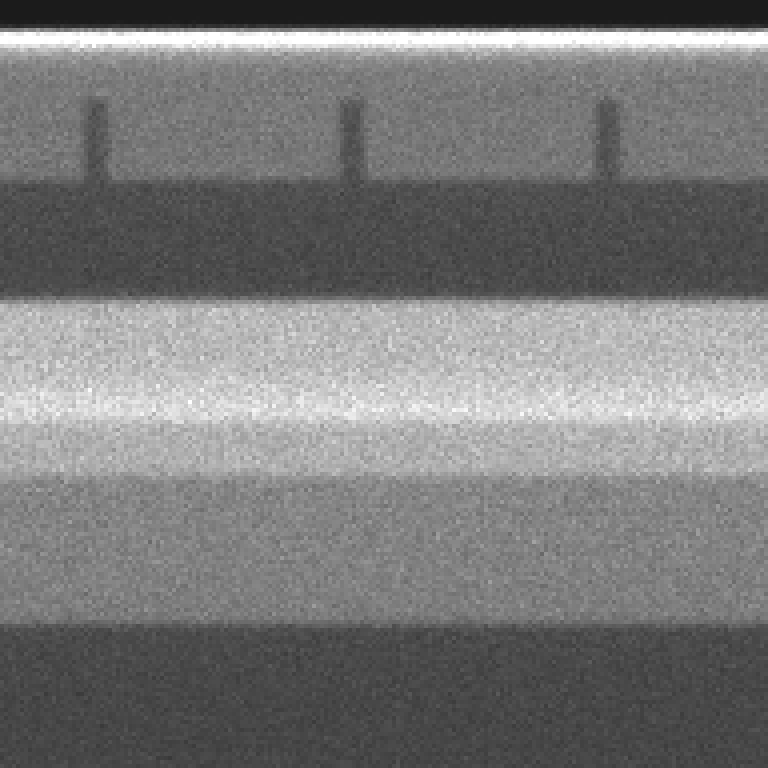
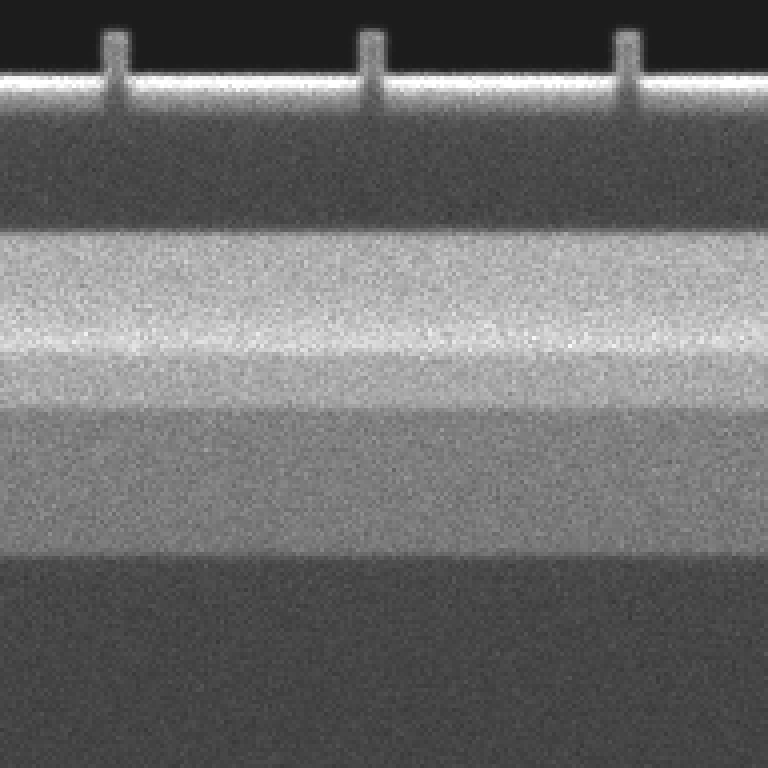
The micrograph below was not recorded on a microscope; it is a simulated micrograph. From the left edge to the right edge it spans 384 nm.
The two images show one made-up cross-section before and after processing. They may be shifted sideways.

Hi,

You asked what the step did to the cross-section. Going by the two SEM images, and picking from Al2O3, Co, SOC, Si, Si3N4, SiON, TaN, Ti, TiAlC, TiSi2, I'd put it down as SOC, removed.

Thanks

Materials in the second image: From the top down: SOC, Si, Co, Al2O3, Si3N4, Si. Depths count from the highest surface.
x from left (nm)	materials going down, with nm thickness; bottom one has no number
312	Si 100, Co 60, Al2O3 28, Si3N4 74, Si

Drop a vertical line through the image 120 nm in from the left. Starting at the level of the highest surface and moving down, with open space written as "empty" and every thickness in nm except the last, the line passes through empty 22, SOC 18, Si 60, Co 60, Al2O3 28, Si3N4 74, Si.